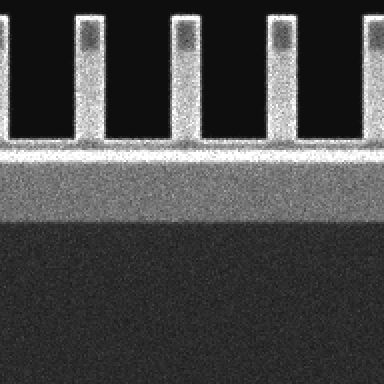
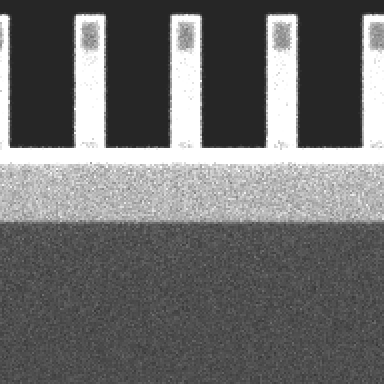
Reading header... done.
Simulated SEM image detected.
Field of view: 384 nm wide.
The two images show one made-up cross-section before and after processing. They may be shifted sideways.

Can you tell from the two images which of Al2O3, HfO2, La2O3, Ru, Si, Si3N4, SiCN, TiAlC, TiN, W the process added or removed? Yes, it removed TiN.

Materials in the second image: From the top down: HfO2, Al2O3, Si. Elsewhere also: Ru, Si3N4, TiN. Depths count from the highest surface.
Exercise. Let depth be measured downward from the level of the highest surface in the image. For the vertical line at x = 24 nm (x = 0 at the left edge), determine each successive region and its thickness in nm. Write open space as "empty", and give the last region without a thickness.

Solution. empty 134, HfO2 12, Al2O3 60, Si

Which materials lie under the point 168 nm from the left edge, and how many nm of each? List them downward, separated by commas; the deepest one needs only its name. empty 134, HfO2 12, Al2O3 60, Si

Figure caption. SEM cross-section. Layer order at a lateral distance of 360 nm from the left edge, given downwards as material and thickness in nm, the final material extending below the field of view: empty 134, HfO2 12, Al2O3 60, Si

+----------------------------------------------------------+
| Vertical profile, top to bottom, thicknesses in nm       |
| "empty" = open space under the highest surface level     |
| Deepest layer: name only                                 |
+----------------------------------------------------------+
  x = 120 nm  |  empty 134, HfO2 12, Al2O3 60, Si